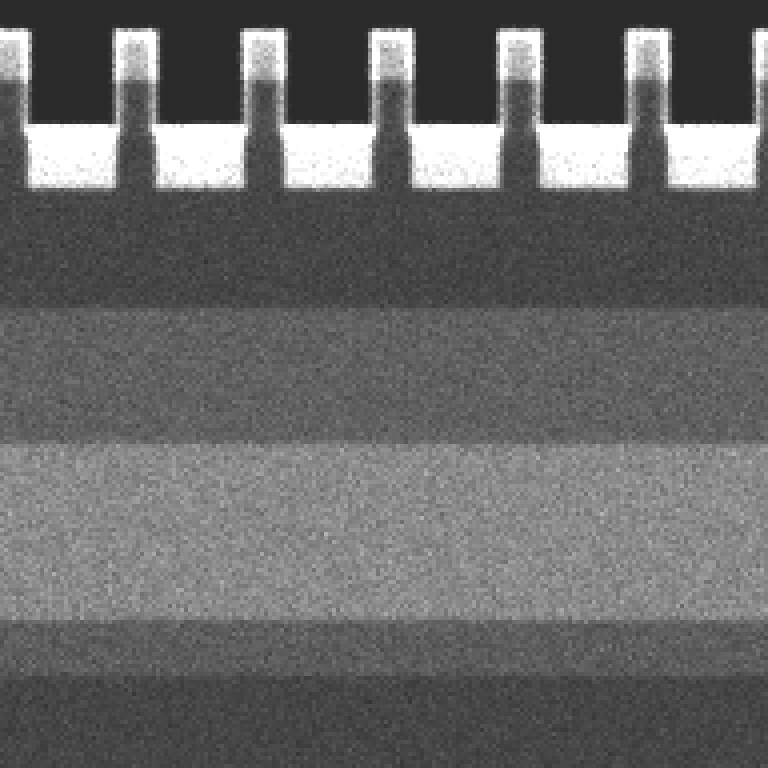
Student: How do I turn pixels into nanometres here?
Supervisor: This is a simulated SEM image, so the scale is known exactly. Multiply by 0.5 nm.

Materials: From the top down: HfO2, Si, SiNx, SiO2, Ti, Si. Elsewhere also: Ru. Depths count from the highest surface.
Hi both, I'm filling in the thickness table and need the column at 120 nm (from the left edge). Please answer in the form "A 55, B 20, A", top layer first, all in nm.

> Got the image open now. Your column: empty 48, HfO2 30, Si 60, SiNx 68, SiO2 88, Ti 28, Si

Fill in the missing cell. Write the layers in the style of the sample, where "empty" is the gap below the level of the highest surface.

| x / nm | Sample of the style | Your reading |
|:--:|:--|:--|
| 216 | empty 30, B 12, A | empty 48, HfO2 30, Si 60, SiNx 68, SiO2 88, Ti 28, Si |